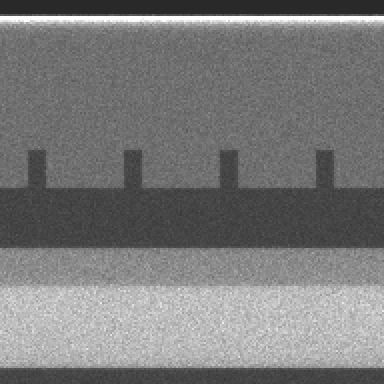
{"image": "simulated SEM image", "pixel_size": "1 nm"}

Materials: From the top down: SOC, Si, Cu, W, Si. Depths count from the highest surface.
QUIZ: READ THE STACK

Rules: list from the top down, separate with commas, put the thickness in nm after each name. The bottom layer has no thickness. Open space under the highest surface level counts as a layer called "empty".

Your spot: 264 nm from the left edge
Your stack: SOC 172, Si 60, Cu 38, W 82, Si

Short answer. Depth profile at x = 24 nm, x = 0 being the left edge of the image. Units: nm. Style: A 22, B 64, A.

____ SOC 172, Si 60, Cu 38, W 82, Si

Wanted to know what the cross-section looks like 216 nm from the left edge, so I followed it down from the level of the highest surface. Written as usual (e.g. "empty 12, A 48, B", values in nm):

SOC 172, Si 60, Cu 38, W 82, Si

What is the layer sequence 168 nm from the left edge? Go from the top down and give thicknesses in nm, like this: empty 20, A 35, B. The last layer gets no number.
SOC 172, Si 60, Cu 38, W 82, Si